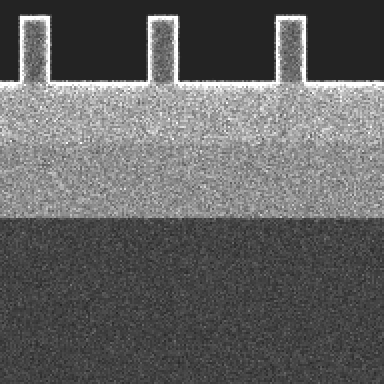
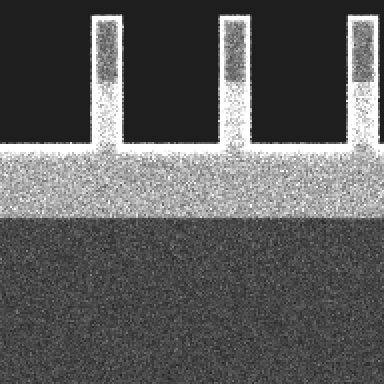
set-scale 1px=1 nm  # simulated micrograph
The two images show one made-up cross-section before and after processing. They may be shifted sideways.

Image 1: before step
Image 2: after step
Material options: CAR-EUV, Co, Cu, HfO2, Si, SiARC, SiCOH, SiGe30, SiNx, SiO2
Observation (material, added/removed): Co, removed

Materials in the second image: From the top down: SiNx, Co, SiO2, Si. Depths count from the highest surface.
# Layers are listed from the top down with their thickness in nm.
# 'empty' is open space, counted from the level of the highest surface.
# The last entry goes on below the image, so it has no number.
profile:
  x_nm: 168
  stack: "empty 128, SiO2 74, Si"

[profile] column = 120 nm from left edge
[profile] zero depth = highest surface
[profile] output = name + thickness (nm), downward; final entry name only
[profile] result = SiNx 66, Co 62, SiO2 74, Si